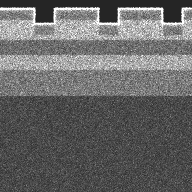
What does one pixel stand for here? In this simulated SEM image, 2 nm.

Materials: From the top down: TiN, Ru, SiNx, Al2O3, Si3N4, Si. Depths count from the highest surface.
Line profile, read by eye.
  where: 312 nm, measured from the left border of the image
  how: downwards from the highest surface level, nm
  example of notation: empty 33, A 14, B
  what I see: TiN 24, Ru 40, SiNx 30, Al2O3 30, Si3N4 52, Si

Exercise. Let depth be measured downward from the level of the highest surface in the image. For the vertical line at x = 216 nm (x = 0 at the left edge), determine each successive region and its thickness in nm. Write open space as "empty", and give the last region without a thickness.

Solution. empty 30, TiN 24, Ru 10, SiNx 30, Al2O3 30, Si3N4 52, Si